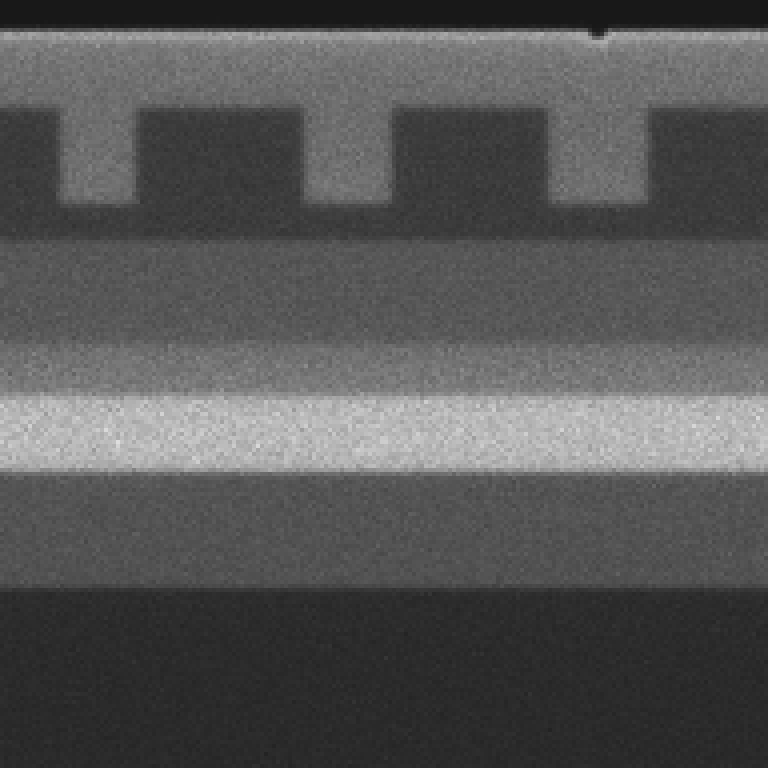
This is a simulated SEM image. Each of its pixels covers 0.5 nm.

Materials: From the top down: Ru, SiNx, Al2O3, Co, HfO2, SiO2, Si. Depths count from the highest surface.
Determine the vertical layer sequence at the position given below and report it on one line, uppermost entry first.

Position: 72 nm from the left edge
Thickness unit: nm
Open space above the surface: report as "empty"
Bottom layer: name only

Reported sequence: Ru 38, SiNx 66, Al2O3 52, Co 26, HfO2 38, SiO2 58, Si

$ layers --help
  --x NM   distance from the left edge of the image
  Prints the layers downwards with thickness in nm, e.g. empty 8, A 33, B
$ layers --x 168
Ru 86, SiNx 18, Al2O3 52, Co 26, HfO2 38, SiO2 58, Si